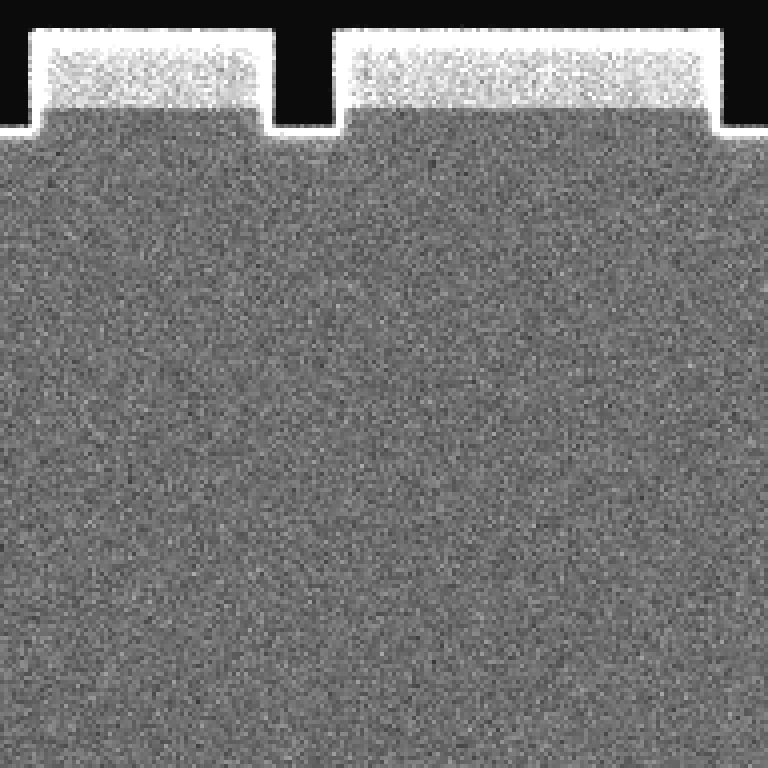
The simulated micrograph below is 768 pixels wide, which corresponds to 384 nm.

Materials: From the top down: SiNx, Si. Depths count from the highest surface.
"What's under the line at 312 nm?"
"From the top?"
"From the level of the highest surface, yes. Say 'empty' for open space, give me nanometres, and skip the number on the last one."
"SiNx 38, Si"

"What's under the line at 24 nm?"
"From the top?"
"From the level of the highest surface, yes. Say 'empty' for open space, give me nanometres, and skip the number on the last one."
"SiNx 38, Si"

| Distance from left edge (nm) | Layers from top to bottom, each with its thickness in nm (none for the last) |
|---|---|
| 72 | SiNx 38, Si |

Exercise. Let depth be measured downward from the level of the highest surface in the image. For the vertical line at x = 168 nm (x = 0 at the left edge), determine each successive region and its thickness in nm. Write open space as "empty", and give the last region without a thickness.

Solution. SiNx 38, Si